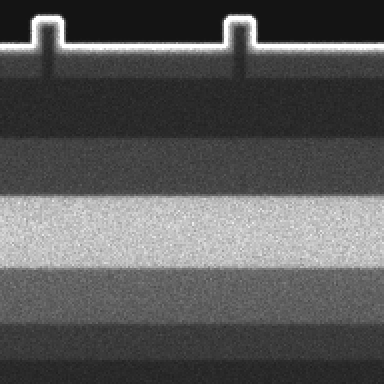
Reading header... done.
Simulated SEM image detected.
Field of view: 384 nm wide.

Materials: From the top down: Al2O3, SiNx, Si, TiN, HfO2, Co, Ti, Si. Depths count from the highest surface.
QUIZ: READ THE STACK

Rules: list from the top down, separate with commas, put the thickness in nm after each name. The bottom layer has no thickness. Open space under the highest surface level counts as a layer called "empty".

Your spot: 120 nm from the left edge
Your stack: empty 28, Al2O3 10, SiNx 24, Si 60, TiN 58, HfO2 72, Co 56, Ti 36, Si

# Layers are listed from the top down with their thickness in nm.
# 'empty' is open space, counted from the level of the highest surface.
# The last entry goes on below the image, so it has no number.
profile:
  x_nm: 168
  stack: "empty 28, Al2O3 10, SiNx 24, Si 60, TiN 58, HfO2 72, Co 56, Ti 36, Si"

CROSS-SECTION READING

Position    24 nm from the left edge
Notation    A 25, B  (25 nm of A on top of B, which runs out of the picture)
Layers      empty 28, Al2O3 10, SiNx 24, Si 60, TiN 58, HfO2 72, Co 56, Ti 36, Si